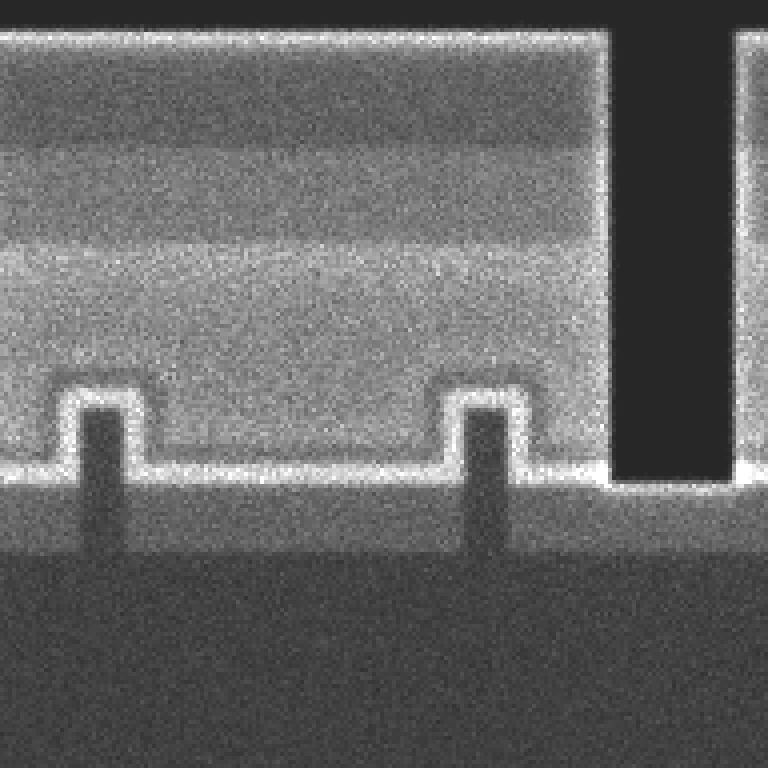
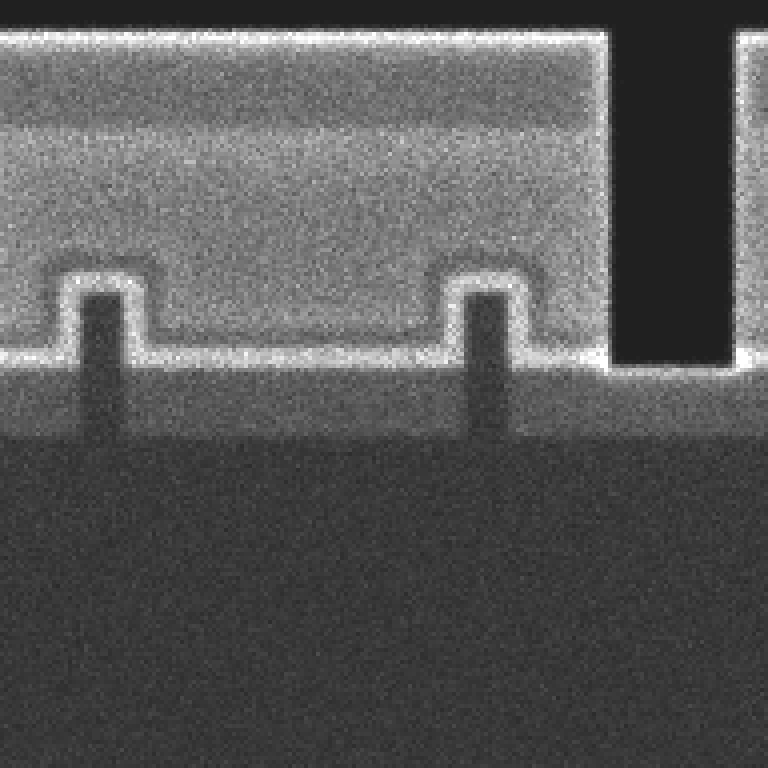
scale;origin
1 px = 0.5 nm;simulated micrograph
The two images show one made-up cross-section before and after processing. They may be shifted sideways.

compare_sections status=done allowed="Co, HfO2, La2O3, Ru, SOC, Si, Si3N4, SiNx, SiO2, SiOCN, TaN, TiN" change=removed material="SOC"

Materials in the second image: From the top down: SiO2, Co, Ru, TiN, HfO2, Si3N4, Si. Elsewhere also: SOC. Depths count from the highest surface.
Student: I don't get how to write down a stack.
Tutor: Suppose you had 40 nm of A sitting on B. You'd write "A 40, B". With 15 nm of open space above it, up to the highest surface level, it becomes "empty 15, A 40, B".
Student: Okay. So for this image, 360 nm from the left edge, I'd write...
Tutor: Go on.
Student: empty 168, Si3N4 34, Si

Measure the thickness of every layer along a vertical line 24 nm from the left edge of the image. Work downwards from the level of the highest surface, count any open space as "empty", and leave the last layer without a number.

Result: SiO2 48, Co 50, Ru 16, TiN 44, HfO2 10, Si3N4 34, Si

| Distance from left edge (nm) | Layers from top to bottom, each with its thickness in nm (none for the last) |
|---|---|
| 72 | SiO2 48, Co 50, Ru 12, TiN 48, HfO2 10, Si3N4 34, Si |